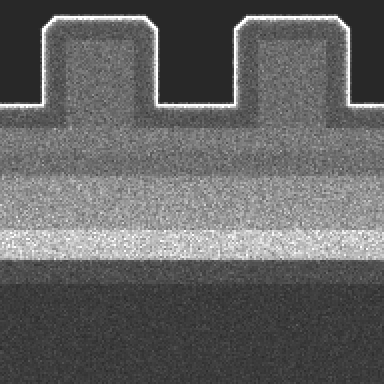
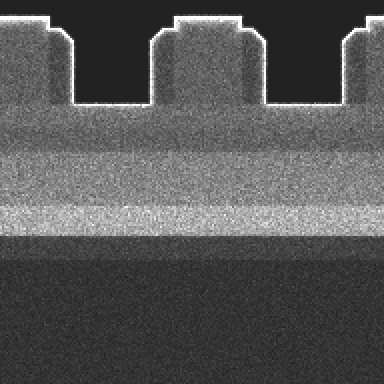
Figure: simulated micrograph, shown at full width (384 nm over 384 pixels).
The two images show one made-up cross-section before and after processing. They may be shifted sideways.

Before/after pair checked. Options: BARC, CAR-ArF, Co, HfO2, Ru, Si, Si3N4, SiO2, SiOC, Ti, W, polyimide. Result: removed Si3N4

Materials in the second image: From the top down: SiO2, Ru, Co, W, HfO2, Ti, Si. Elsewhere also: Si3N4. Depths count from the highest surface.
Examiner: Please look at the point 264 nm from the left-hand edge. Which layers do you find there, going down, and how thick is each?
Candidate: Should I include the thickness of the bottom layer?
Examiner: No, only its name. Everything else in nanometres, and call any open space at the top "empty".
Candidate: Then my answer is empty 24, Si3N4 64, Ru 24, Co 24, W 54, HfO2 30, Ti 24, Si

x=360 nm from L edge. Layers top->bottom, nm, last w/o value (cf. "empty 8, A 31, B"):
empty 12, Si3N4 76, Ru 24, Co 24, W 54, HfO2 30, Ti 24, Si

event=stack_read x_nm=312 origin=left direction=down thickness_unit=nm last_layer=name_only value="empty 88, Ru 24, Co 24, W 54, HfO2 30, Ti 24, Si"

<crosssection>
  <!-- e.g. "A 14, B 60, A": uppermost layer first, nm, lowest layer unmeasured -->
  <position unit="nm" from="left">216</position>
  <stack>SiO2 88, Ru 24, Co 24, W 54, HfO2 30, Ti 24, Si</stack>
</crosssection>